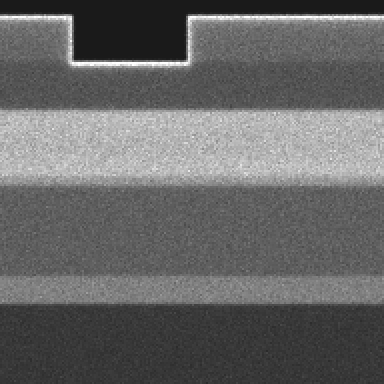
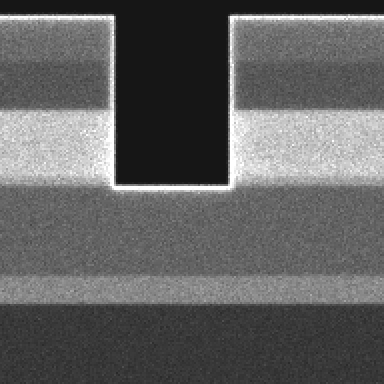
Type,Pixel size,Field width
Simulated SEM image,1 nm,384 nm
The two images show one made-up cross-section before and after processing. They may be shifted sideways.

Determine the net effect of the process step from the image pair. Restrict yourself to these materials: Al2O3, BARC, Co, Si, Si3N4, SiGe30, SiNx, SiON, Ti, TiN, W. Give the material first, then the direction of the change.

Co and SiNx and W: removed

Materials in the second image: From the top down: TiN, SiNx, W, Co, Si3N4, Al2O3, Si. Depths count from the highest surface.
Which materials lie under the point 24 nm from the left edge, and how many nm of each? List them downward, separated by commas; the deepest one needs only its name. TiN 46, SiNx 48, W 66, Co 10, Si3N4 90, Al2O3 28, Si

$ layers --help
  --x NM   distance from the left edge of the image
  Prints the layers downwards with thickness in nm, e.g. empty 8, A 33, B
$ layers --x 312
TiN 46, SiNx 48, W 66, Co 10, Si3N4 90, Al2O3 28, Si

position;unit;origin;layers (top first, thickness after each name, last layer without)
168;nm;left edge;empty 170, Si3N4 90, Al2O3 28, Si